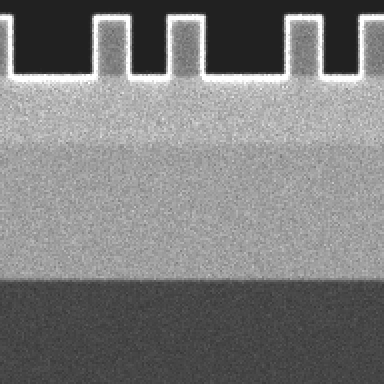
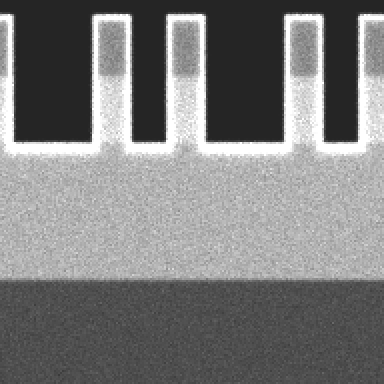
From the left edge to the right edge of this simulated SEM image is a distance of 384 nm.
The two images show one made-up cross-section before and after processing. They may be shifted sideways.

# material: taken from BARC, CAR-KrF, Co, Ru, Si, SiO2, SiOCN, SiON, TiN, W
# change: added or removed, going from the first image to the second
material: Co
change: removed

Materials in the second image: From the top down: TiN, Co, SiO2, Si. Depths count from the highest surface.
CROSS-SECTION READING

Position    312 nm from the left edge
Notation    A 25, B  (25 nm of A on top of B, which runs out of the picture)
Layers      TiN 60, Co 68, SiO2 136, Si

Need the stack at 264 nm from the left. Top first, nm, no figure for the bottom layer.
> empty 128, SiO2 136, Si